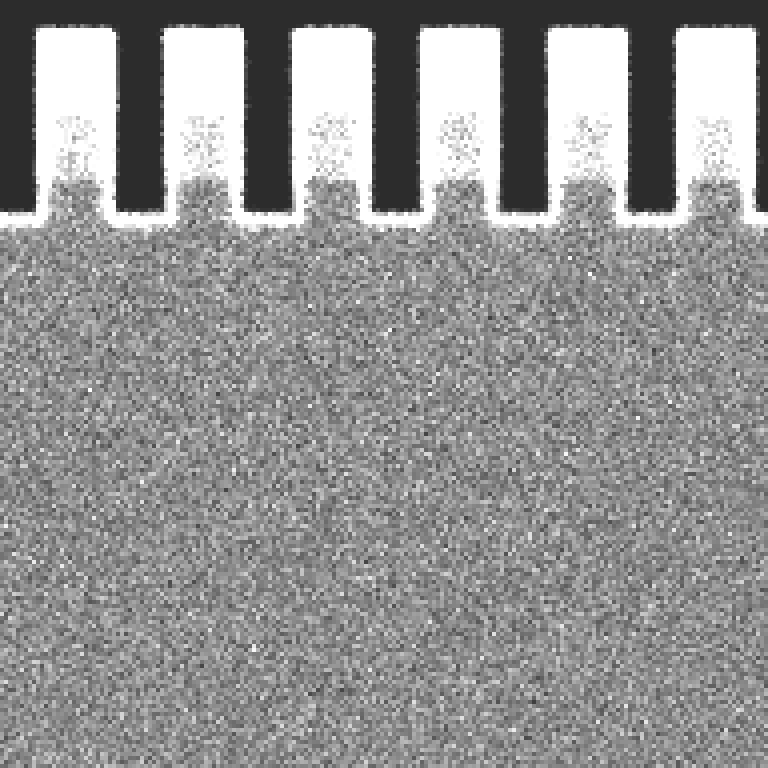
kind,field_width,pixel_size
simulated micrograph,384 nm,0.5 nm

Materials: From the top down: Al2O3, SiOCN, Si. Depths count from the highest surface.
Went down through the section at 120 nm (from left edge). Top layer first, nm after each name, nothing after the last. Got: empty 92, Si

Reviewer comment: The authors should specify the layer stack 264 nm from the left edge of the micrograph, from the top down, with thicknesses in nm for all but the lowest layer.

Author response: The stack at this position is empty 92, Si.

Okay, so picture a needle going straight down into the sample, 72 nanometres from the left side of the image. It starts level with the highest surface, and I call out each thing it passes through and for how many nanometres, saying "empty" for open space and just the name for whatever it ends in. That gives empty 92, Si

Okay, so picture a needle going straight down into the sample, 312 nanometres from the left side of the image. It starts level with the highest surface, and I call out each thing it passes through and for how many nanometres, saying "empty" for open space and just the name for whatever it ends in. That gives empty 92, Si